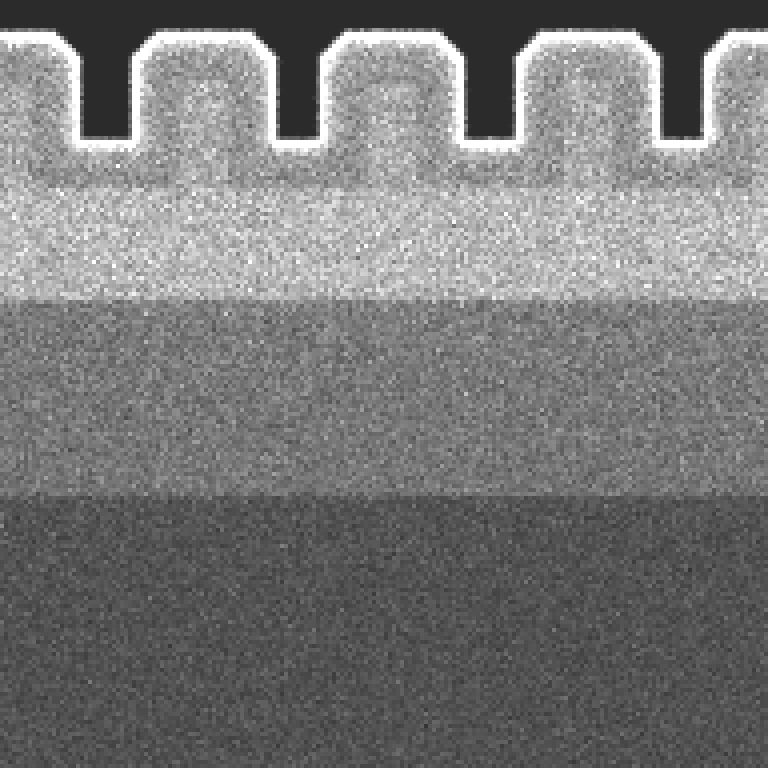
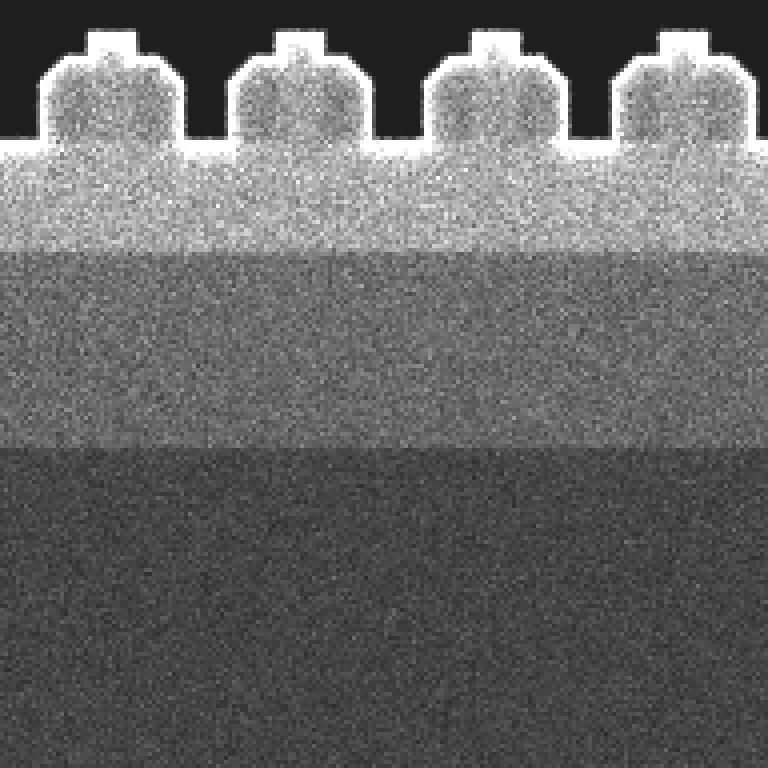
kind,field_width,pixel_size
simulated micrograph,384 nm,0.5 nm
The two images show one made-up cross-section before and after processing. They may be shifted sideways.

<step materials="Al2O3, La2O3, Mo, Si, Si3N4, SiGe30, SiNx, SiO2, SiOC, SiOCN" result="removed Si3N4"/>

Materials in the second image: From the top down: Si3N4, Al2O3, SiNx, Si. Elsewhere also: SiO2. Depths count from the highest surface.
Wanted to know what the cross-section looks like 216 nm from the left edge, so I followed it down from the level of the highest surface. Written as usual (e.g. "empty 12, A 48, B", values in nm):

empty 20, Si3N4 34, Al2O3 56, SiNx 98, Si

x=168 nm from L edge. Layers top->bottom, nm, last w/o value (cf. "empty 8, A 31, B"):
empty 12, Si3N4 42, Al2O3 56, SiNx 98, Si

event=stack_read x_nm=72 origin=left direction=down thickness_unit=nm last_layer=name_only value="empty 12, Si3N4 42, Al2O3 56, SiNx 98, Si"